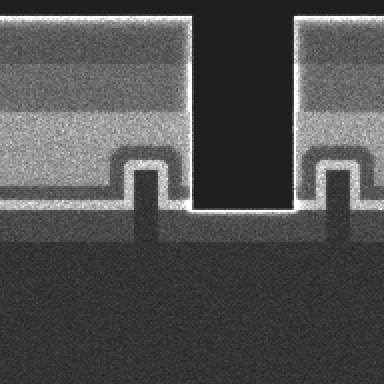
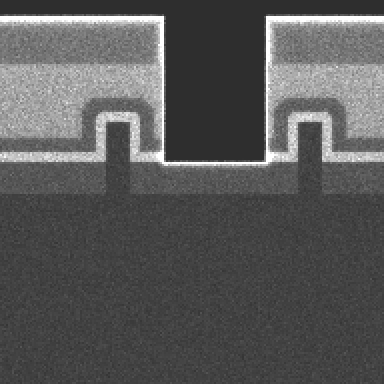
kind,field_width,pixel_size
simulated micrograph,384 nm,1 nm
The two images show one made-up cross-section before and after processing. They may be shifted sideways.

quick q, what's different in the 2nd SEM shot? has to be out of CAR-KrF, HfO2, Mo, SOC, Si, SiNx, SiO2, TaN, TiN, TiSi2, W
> SOC removed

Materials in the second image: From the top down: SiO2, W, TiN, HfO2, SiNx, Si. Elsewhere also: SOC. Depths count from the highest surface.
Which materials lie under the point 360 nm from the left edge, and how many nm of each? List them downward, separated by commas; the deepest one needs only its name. SiO2 48, W 74, TiN 14, HfO2 10, SiNx 32, Si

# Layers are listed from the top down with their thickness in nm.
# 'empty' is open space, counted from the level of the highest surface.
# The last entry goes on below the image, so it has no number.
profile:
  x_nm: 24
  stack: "SiO2 48, W 74, TiN 14, HfO2 10, SiNx 32, Si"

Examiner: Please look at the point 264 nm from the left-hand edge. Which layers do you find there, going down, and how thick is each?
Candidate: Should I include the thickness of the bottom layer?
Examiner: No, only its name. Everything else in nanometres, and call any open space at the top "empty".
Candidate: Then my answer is empty 146, SiNx 32, Si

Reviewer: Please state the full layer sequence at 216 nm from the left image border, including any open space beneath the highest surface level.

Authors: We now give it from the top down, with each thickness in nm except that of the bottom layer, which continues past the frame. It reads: empty 146, SiNx 32, Si